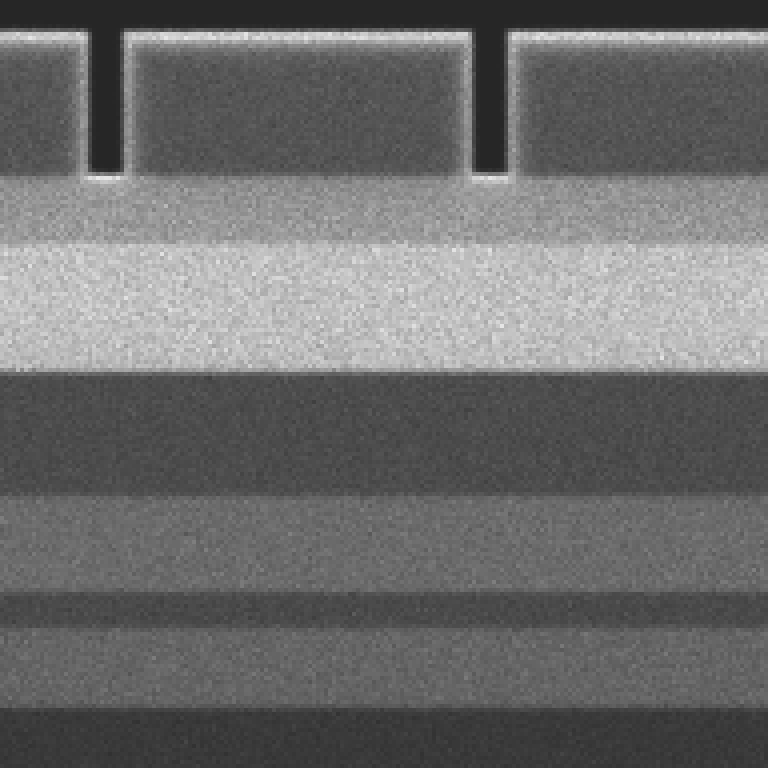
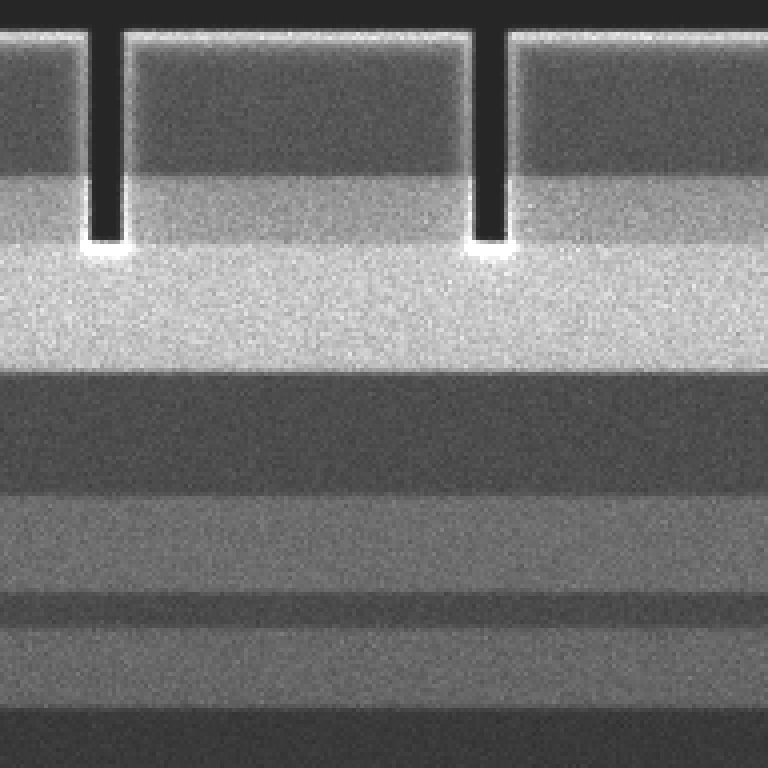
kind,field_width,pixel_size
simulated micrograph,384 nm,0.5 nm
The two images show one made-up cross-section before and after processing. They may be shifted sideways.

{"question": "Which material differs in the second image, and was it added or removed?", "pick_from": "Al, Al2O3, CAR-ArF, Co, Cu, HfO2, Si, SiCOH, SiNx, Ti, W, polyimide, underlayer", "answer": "W, removed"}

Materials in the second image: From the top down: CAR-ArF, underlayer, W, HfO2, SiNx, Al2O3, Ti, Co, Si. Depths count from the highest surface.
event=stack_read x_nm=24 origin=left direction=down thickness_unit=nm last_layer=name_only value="CAR-ArF 44, underlayer 28, W 34, HfO2 64, SiNx 62, Al2O3 48, Ti 18, Co 40, Si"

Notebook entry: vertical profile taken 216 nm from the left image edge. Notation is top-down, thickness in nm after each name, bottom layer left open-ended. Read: CAR-ArF 44, underlayer 28, W 34, HfO2 64, SiNx 62, Al2O3 48, Ti 18, Co 40, Si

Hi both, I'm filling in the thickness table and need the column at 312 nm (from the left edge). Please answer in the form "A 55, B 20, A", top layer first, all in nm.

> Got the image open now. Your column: CAR-ArF 44, underlayer 28, W 34, HfO2 64, SiNx 62, Al2O3 48, Ti 18, Co 40, Si